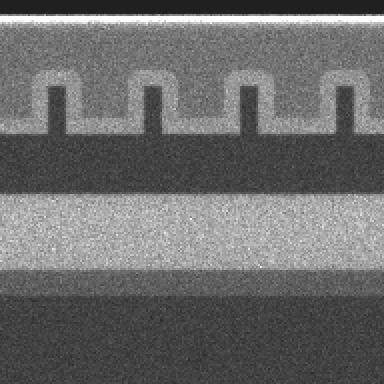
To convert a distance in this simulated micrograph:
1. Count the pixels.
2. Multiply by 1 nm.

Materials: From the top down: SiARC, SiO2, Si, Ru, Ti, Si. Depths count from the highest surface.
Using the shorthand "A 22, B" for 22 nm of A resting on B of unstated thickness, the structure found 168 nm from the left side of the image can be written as SiARC 54, SiO2 64, Si 60, Ru 76, Ti 26, Si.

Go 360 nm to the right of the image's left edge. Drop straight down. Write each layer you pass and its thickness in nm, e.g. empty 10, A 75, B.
SiARC 54, SiO2 64, Si 60, Ru 76, Ti 26, Si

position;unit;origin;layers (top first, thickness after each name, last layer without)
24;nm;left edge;SiARC 102, SiO2 16, Si 60, Ru 76, Ti 26, Si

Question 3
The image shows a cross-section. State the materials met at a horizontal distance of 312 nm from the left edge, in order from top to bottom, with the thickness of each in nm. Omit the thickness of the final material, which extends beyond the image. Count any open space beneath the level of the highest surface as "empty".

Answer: SiARC 102, SiO2 16, Si 60, Ru 76, Ti 26, Si